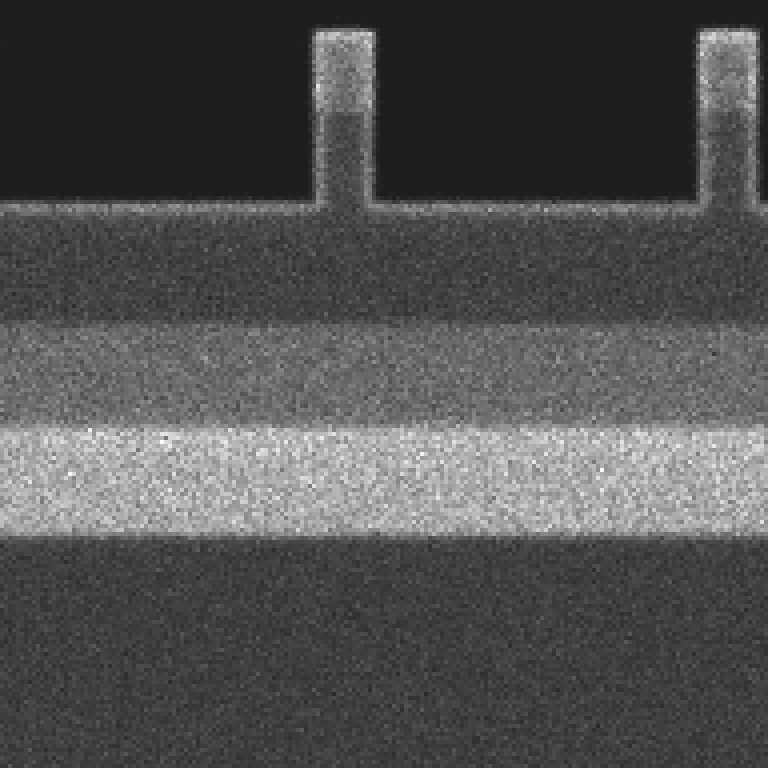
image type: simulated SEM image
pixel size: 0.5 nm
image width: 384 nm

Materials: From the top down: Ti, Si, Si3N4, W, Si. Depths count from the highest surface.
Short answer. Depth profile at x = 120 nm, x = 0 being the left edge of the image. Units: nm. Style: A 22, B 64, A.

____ empty 86, Si 60, Si3N4 52, W 54, Si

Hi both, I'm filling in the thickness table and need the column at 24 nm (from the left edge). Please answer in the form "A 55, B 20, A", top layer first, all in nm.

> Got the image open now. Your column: empty 86, Si 60, Si3N4 52, W 54, Si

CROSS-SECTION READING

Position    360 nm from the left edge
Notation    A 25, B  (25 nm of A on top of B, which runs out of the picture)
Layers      Ti 40, Si 106, Si3N4 52, W 54, Si